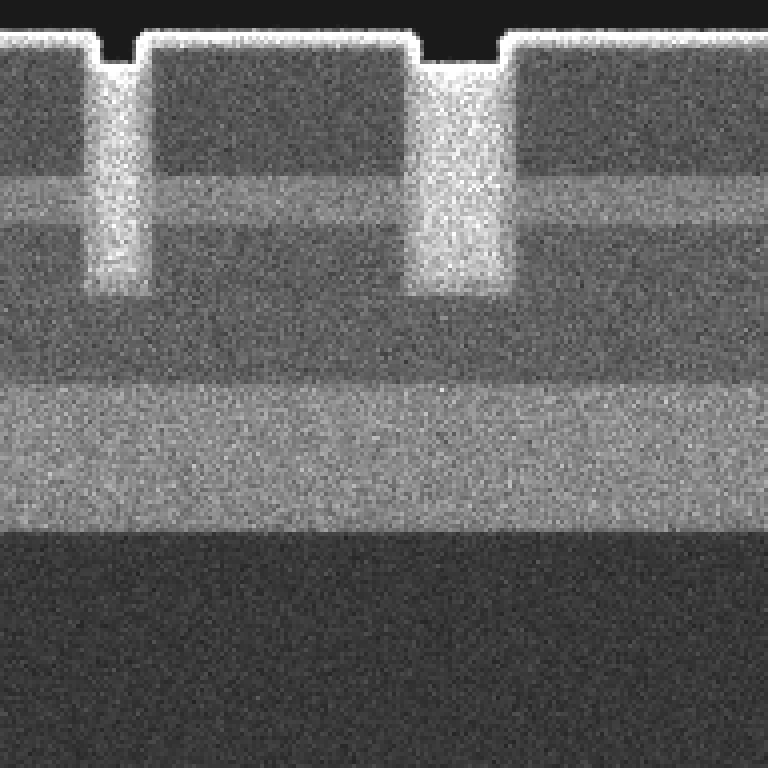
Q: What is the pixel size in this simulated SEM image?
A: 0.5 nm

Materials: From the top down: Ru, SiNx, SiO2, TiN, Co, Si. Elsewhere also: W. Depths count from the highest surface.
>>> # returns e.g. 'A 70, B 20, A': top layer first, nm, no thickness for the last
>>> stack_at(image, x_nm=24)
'Ru 8, SiNx 64, SiO2 24, TiN 80, Co 74, Si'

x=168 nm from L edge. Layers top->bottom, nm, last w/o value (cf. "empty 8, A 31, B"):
Ru 8, SiNx 64, SiO2 24, TiN 80, Co 74, Si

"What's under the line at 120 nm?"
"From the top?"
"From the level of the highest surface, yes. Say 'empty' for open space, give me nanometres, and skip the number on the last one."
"Ru 8, SiNx 64, SiO2 24, TiN 80, Co 74, Si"